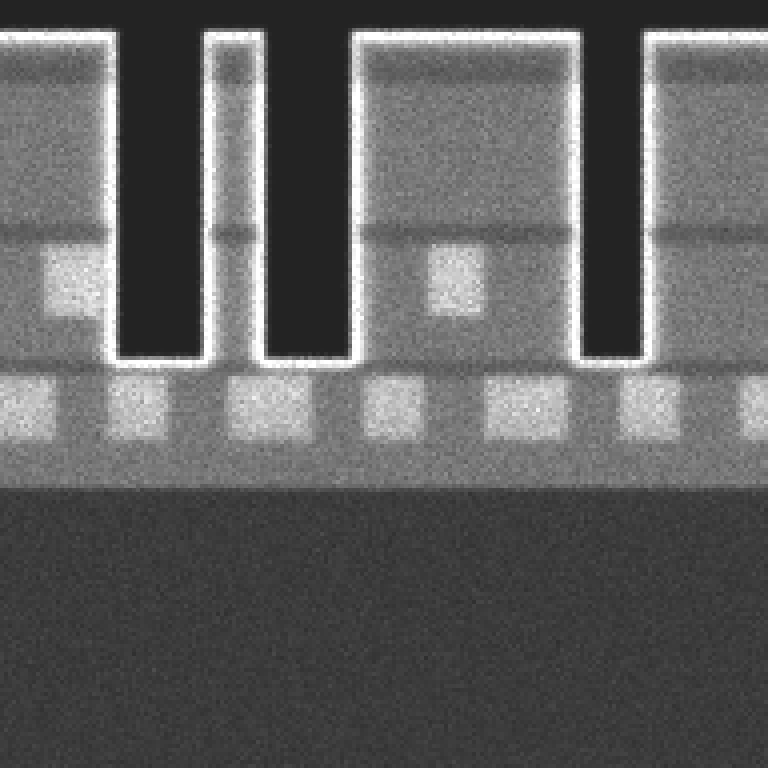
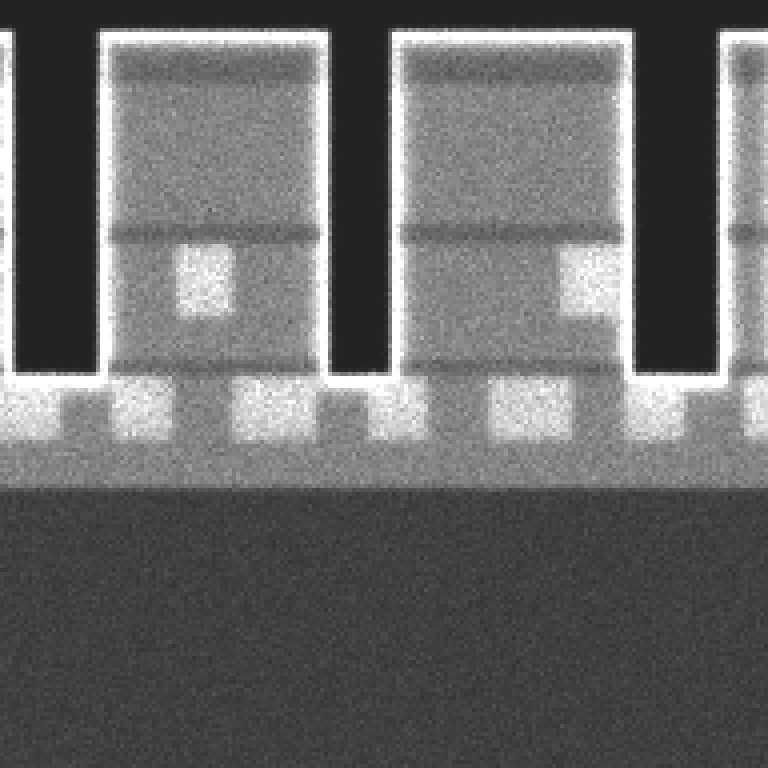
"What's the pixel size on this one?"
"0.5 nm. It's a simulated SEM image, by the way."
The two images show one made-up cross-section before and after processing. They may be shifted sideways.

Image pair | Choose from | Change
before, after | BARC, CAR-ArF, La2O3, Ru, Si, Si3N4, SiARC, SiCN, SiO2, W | Si3N4 (removed)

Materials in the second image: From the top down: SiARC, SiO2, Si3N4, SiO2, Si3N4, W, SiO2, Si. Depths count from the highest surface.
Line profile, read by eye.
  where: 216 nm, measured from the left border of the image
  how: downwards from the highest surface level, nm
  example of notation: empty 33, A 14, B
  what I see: SiARC 26, SiO2 70, Si3N4 10, SiO2 58, Si3N4 8, SiO2 56, Si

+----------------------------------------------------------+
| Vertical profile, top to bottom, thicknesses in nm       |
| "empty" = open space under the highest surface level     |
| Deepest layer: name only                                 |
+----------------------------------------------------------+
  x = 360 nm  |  SiARC 26, SiO2 70, Si3N4 10, SiO2 58, Si3N4 8, SiO2 56, Si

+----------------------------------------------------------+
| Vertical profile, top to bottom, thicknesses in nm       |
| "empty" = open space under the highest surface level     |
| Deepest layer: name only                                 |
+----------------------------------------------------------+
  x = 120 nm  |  SiARC 26, SiO2 70, Si3N4 10, SiO2 58, Si3N4 8, W 32, SiO2 24, Si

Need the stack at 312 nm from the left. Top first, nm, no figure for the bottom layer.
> SiARC 26, SiO2 70, Si3N4 10, SiO2 58, Si3N4 8, W 32, SiO2 24, Si